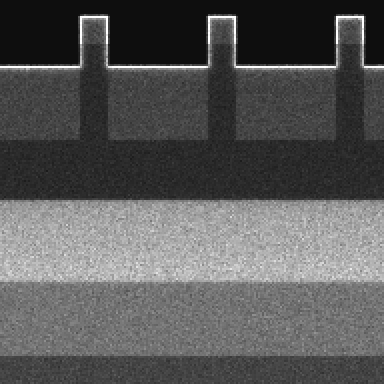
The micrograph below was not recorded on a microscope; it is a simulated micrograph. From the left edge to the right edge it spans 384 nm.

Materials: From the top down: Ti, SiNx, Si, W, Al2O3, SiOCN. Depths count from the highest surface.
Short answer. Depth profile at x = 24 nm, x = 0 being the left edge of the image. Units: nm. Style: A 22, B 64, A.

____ empty 50, Ti 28, SiNx 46, Si 60, W 82, Al2O3 74, SiOCN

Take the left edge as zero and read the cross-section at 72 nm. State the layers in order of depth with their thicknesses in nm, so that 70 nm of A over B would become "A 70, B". empty 50, Ti 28, SiNx 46, Si 60, W 82, Al2O3 74, SiOCN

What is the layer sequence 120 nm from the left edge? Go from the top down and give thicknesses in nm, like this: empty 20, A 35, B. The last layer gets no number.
empty 50, Ti 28, SiNx 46, Si 60, W 82, Al2O3 74, SiOCN